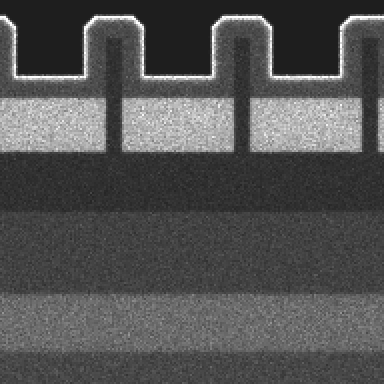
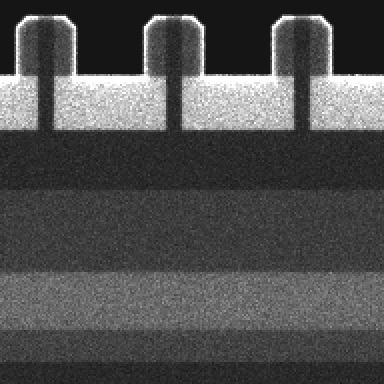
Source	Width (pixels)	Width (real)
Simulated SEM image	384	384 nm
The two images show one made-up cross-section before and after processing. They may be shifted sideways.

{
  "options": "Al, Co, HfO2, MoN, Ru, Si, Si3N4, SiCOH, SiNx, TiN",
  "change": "removed",
  "material": "Si3N4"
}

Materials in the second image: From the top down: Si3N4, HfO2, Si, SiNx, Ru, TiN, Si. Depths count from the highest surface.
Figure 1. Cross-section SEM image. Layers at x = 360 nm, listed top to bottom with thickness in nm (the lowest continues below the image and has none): empty 60, HfO2 54, Si 60, SiNx 82, Ru 58, TiN 32, Si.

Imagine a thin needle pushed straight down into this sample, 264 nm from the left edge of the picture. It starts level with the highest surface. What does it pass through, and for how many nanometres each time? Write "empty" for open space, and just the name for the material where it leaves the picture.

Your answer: empty 60, HfO2 54, Si 60, SiNx 82, Ru 58, TiN 32, Si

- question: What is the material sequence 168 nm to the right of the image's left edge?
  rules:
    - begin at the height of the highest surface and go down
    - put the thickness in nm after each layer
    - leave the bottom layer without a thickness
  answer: Si 174, SiNx 82, Ru 58, TiN 32, Si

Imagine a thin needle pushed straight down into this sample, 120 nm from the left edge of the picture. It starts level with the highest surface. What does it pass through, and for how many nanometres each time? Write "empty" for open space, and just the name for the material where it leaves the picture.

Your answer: empty 60, HfO2 54, Si 60, SiNx 82, Ru 58, TiN 32, Si